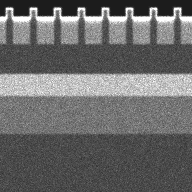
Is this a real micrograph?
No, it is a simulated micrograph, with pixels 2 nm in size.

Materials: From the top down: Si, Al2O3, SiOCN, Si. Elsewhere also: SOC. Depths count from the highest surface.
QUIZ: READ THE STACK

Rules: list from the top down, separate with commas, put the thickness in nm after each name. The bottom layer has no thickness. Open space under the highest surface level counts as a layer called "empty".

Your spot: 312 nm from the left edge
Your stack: Si 132, Al2O3 44, SiOCN 76, Si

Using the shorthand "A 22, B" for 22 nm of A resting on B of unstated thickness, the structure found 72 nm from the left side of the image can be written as Si 132, Al2O3 44, SiOCN 76, Si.